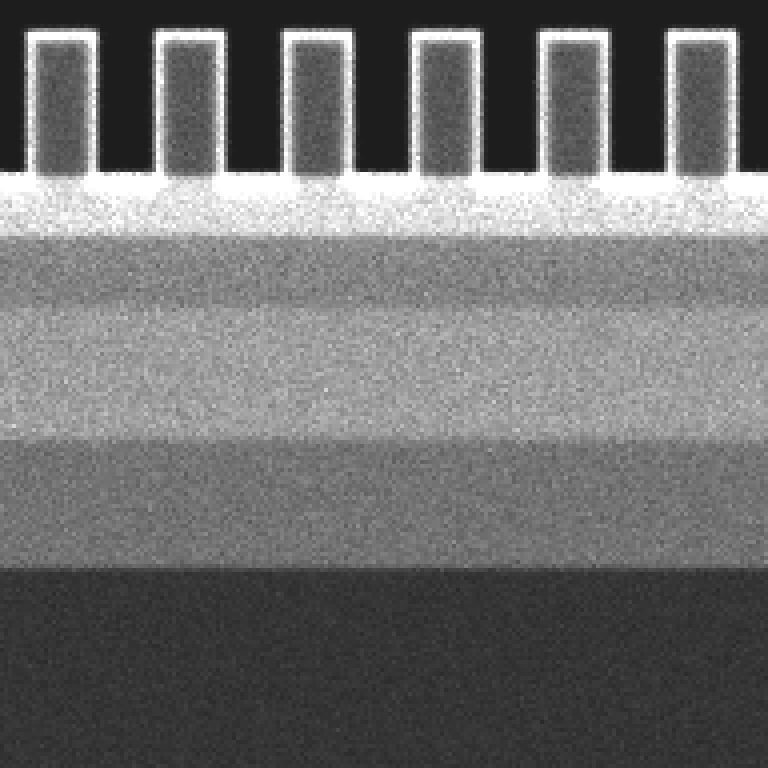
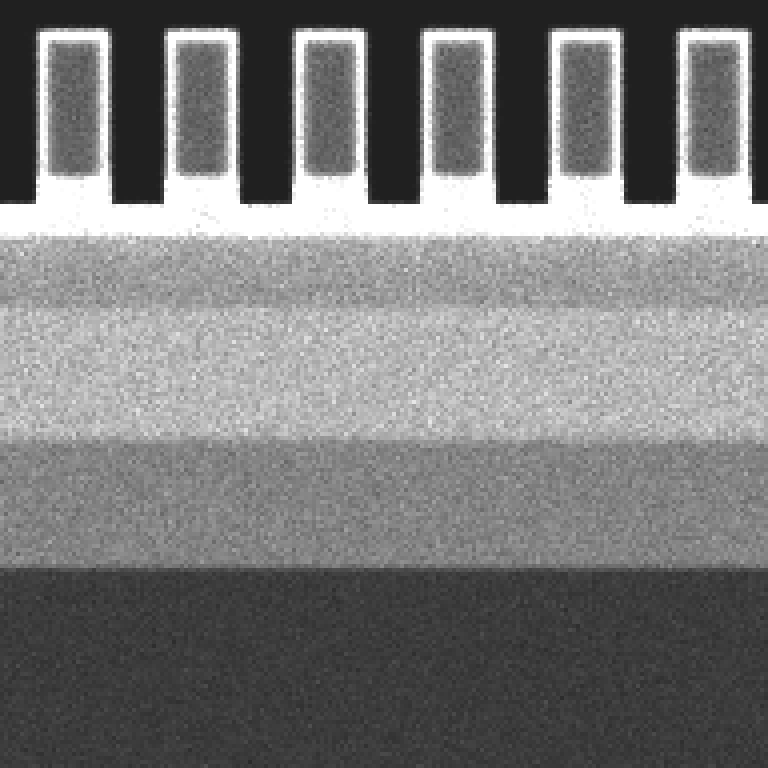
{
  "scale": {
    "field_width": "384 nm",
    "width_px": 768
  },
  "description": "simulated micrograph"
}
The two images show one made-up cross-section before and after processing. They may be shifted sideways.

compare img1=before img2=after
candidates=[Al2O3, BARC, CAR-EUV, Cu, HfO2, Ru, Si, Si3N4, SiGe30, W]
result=removed:HfO2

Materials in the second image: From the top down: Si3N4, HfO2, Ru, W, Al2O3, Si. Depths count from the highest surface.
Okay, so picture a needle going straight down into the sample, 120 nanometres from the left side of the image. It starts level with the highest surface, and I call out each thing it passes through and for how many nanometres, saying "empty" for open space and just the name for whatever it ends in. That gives empty 88, HfO2 14, Ru 36, W 66, Al2O3 64, Si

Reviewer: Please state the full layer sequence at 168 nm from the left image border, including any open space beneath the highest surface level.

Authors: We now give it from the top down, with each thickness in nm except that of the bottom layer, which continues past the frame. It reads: Si3N4 72, HfO2 30, Ru 36, W 66, Al2O3 64, Si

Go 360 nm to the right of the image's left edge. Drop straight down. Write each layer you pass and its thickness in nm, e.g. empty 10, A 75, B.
Si3N4 72, HfO2 30, Ru 36, W 66, Al2O3 64, Si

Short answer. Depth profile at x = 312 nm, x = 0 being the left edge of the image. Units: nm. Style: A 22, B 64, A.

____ empty 88, HfO2 14, Ru 36, W 66, Al2O3 64, Si